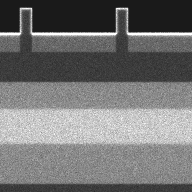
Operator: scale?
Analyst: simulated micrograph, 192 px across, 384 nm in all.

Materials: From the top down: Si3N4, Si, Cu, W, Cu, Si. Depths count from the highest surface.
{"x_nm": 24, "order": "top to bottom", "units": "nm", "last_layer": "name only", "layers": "empty 50, Si3N4 38, Si 60, Cu 54, W 70, Cu 80, Si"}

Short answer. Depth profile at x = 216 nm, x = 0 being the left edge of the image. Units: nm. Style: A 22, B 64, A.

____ empty 50, Si3N4 38, Si 60, Cu 54, W 70, Cu 80, Si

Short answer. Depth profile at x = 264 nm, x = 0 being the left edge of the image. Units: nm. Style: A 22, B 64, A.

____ empty 50, Si3N4 38, Si 60, Cu 54, W 70, Cu 80, Si